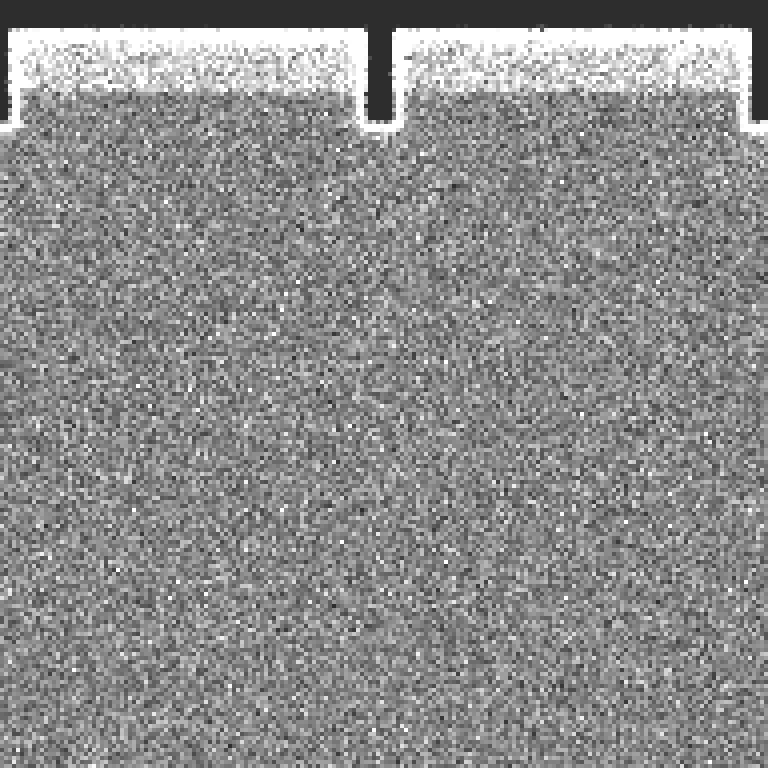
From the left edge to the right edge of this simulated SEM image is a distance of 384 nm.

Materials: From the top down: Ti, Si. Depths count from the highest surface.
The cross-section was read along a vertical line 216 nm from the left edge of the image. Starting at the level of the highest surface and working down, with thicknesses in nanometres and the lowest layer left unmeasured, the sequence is Ti 30, Si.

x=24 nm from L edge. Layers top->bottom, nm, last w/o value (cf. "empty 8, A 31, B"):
Ti 30, Si